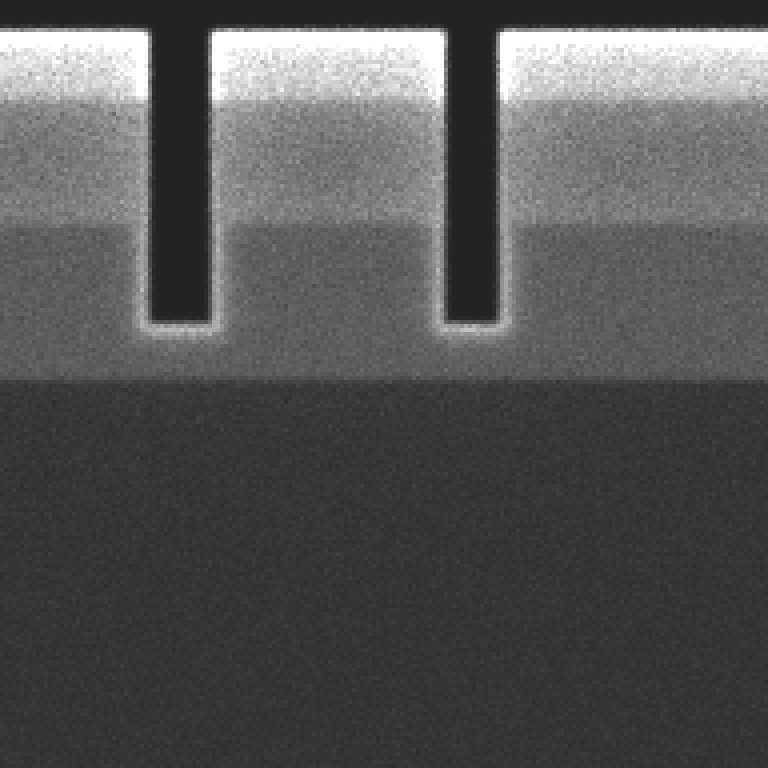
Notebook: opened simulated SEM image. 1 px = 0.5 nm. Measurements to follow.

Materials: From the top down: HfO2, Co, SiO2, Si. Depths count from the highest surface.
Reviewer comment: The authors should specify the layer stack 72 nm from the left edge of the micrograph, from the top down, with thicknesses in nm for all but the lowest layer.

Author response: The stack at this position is HfO2 34, Co 62, SiO2 78, Si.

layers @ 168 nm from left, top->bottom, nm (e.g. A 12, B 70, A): HfO2 34, Co 62, SiO2 78, Si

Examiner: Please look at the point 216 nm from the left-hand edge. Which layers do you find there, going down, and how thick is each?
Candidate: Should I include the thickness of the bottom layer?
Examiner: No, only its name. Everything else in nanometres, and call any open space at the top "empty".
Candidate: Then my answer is HfO2 34, Co 62, SiO2 78, Si